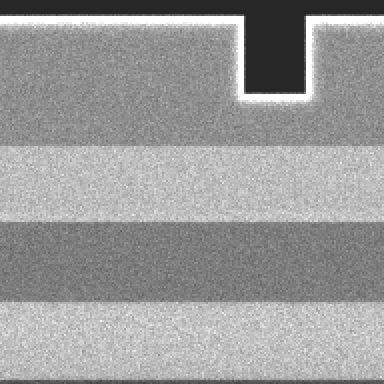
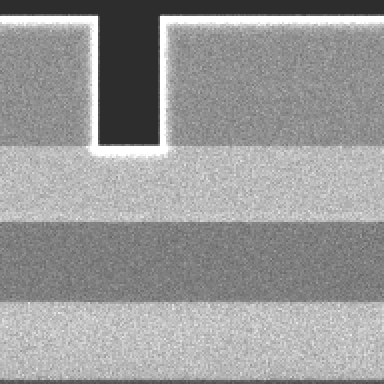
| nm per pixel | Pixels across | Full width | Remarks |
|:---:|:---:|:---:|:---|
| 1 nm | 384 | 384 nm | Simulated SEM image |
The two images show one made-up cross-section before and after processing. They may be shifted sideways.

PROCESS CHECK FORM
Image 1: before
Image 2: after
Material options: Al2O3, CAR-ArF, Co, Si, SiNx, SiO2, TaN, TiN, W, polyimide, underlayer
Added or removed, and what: removed, underlayer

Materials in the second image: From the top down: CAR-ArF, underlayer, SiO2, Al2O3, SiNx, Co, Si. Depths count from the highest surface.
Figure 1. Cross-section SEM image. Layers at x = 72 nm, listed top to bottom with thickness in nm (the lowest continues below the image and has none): CAR-ArF 78, underlayer 52, SiO2 66, Al2O3 10, SiNx 80, Co 78, Si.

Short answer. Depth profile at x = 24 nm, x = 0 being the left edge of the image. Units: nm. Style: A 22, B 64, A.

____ CAR-ArF 78, underlayer 52, SiO2 66, Al2O3 10, SiNx 80, Co 78, Si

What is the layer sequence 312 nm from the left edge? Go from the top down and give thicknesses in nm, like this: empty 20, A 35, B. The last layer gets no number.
CAR-ArF 78, underlayer 52, SiO2 66, Al2O3 10, SiNx 80, Co 78, Si